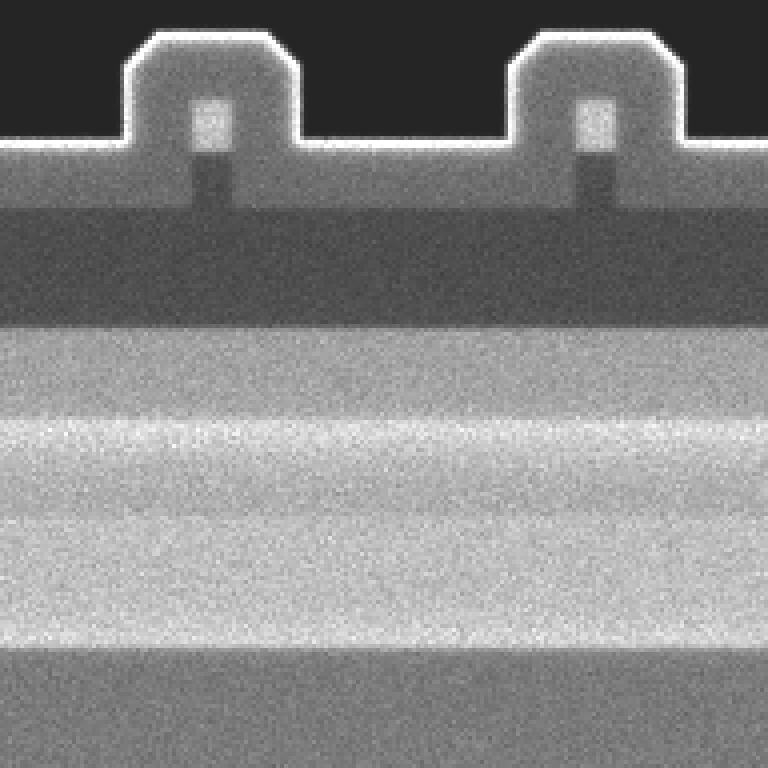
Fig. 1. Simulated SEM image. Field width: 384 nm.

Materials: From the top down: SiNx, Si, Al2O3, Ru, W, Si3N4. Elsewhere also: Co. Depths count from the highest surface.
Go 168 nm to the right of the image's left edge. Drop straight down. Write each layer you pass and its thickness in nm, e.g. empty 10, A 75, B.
empty 54, SiNx 34, Si 60, Al2O3 46, Ru 48, W 66, Si3N4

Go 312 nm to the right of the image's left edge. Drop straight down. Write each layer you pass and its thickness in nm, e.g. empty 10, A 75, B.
SiNx 88, Si 60, Al2O3 46, Ru 48, W 66, Si3N4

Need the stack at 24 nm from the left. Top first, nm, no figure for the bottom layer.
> empty 54, SiNx 34, Si 60, Al2O3 46, Ru 48, W 66, Si3N4